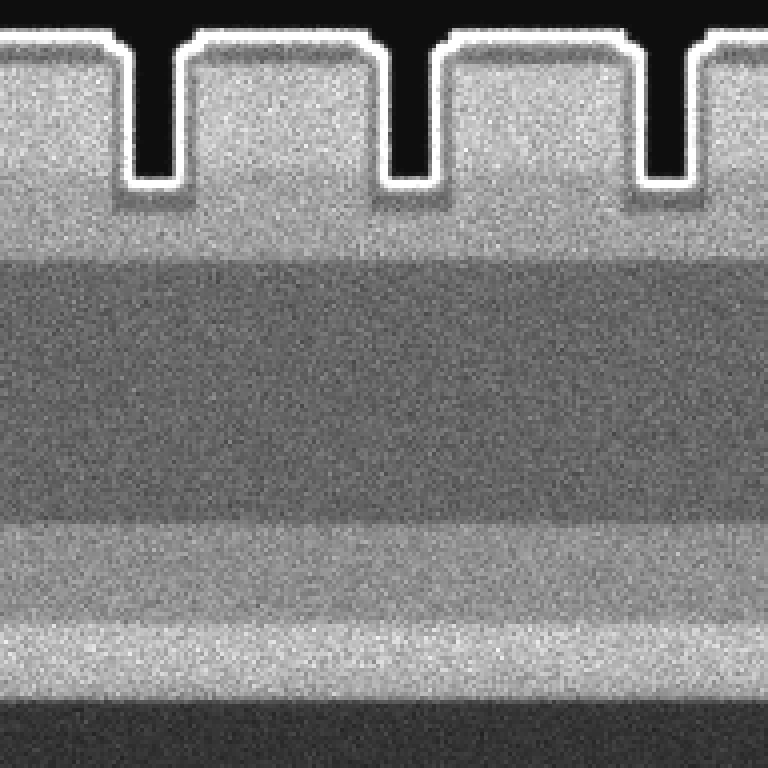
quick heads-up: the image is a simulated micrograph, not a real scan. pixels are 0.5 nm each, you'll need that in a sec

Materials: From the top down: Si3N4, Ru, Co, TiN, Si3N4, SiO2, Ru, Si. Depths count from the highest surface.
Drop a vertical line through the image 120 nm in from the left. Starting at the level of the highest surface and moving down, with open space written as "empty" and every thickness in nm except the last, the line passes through Si3N4 16, Ru 52, Co 46, TiN 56, Si3N4 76, SiO2 50, Ru 38, Si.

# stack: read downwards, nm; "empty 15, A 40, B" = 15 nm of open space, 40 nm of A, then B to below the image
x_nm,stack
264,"Si3N4 16, Ru 52, Co 46, TiN 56, Si3N4 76, SiO2 50, Ru 38, Si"